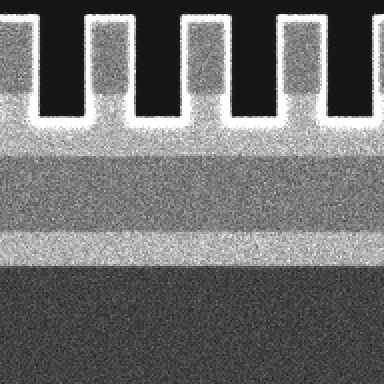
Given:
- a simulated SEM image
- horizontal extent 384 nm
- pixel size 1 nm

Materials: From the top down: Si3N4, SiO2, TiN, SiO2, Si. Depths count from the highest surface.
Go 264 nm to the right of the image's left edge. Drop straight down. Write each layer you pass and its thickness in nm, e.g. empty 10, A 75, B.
empty 102, SiO2 38, TiN 76, SiO2 34, Si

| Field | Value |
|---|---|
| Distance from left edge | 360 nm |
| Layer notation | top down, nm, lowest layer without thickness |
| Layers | empty 102, SiO2 38, TiN 76, SiO2 34, Si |